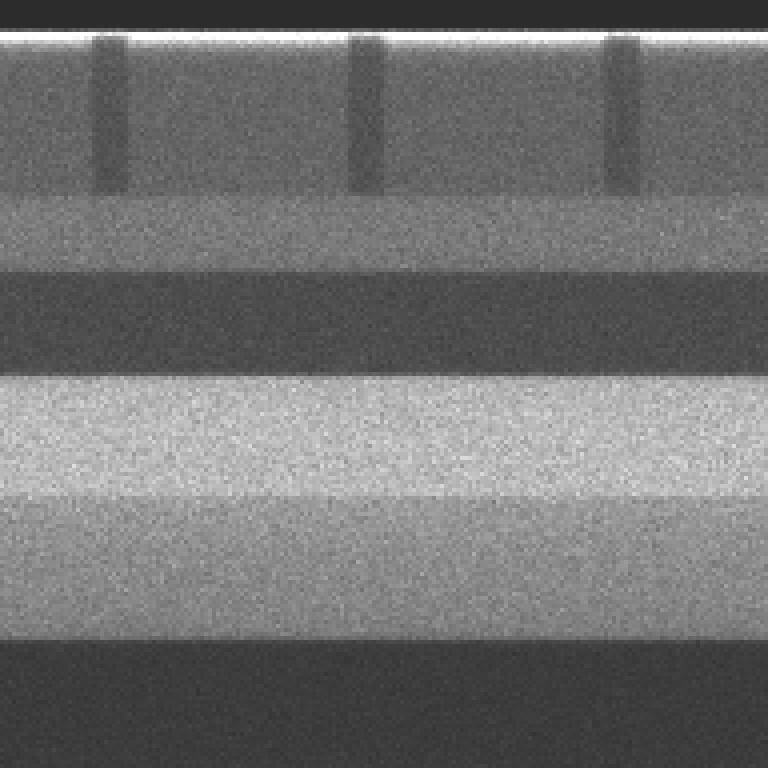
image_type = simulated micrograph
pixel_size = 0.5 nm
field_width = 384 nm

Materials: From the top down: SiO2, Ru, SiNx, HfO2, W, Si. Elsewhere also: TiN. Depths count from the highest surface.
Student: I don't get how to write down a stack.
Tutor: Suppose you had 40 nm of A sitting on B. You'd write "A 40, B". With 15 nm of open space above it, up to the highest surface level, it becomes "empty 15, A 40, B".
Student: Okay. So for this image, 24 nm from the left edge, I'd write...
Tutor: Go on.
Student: SiO2 82, Ru 38, SiNx 52, HfO2 60, W 72, Si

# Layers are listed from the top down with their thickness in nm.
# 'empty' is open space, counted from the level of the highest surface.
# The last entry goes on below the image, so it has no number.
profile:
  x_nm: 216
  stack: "SiO2 82, Ru 38, SiNx 52, HfO2 60, W 72, Si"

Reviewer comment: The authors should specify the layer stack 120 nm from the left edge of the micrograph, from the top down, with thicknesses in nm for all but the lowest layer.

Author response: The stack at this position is SiO2 82, Ru 38, SiNx 52, HfO2 60, W 72, Si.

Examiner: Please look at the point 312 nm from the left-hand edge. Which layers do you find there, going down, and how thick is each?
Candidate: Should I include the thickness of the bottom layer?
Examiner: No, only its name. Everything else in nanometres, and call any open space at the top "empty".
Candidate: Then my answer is TiN 82, Ru 38, SiNx 52, HfO2 60, W 72, Si